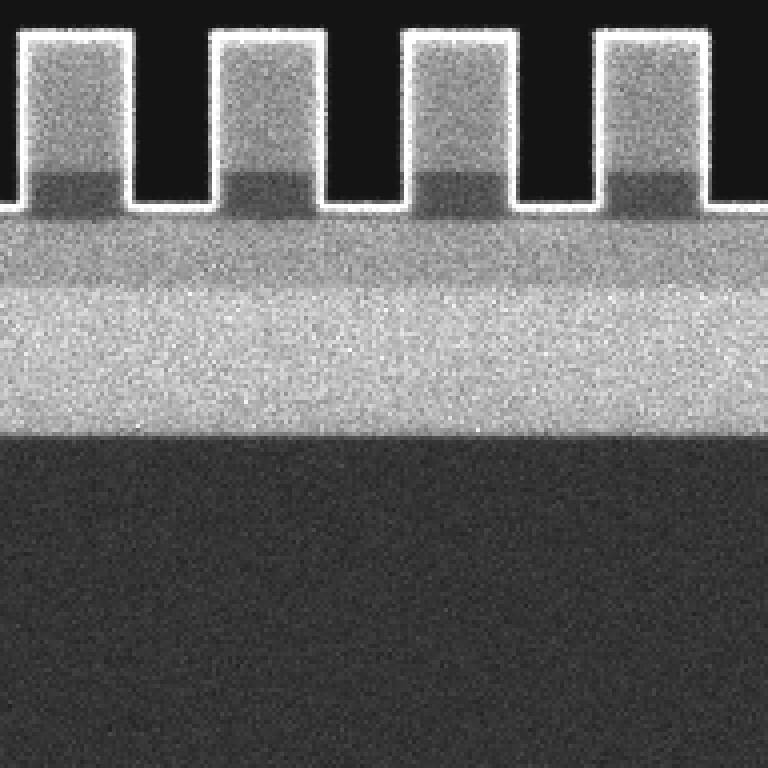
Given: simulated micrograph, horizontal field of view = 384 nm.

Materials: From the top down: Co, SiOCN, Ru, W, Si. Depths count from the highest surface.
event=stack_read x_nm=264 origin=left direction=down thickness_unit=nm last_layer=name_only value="empty 86, SiOCN 8, Ru 34, W 74, Si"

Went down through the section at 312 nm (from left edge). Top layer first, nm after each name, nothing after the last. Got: Co 70, SiOCN 24, Ru 34, W 74, Si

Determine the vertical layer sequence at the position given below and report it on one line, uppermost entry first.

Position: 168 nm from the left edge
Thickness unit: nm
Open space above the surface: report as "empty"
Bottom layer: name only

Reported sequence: empty 86, SiOCN 8, Ru 34, W 74, Si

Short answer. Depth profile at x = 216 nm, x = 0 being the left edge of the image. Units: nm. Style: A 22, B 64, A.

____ Co 70, SiOCN 24, Ru 34, W 74, Si